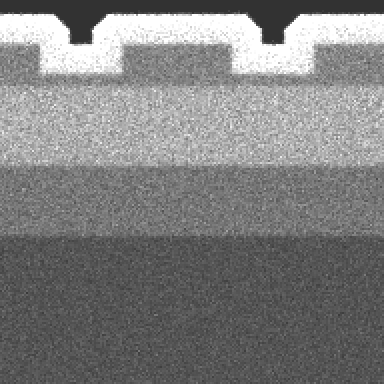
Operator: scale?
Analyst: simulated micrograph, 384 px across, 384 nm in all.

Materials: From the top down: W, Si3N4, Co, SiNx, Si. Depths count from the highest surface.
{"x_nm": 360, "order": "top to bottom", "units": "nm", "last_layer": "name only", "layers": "W 28, Si3N4 42, Co 80, SiNx 70, Si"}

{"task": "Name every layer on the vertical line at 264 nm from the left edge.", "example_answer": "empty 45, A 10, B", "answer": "empty 30, W 28, Si3N4 12, Co 80, SiNx 70, Si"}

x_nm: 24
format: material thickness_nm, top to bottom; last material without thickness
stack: W 28, Si3N4 42, Co 80, SiNx 70, Si